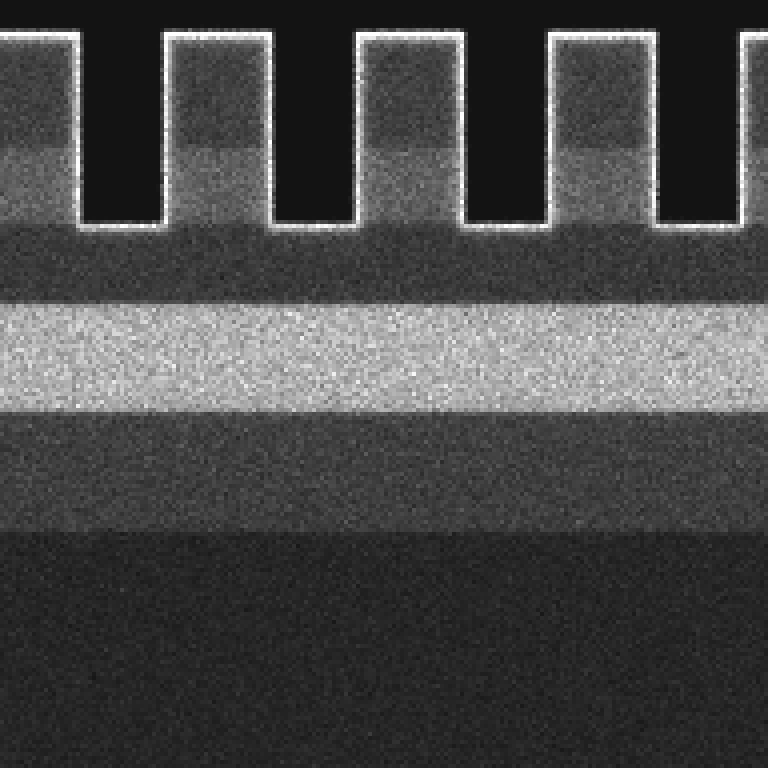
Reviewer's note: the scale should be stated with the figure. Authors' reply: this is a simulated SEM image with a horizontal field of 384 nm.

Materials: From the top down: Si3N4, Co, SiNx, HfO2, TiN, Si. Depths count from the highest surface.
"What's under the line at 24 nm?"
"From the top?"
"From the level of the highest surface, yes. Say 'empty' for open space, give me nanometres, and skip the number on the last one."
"Si3N4 58, Co 38, SiNx 40, HfO2 54, TiN 60, Si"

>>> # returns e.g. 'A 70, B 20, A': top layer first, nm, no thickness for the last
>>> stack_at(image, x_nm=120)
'Si3N4 58, Co 38, SiNx 40, HfO2 54, TiN 60, Si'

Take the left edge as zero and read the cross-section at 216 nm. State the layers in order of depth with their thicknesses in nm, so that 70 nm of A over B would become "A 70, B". Si3N4 58, Co 38, SiNx 40, HfO2 54, TiN 60, Si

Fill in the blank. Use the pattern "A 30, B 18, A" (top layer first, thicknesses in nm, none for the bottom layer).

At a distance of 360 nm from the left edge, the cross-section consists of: empty 96, SiNx 40, HfO2 54, TiN 60, Si